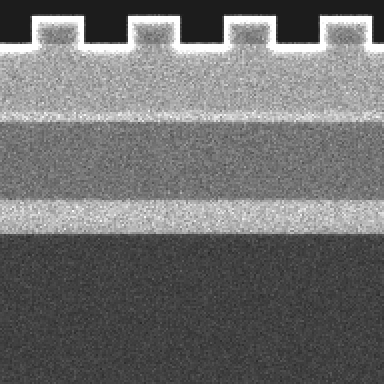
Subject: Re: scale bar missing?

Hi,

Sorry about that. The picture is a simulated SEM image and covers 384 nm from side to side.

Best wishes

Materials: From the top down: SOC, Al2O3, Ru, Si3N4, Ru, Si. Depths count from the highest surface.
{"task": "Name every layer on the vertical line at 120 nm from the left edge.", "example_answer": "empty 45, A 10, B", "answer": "empty 28, Al2O3 68, Ru 10, Si3N4 78, Ru 34, Si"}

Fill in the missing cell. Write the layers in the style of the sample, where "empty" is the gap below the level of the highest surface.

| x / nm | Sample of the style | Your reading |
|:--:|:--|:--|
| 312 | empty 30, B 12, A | empty 28, Al2O3 68, Ru 10, Si3N4 78, Ru 34, Si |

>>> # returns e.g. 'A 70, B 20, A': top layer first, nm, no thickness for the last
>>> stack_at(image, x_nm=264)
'SOC 28, Al2O3 68, Ru 10, Si3N4 78, Ru 34, Si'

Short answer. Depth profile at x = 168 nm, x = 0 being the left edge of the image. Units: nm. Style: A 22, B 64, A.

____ SOC 28, Al2O3 68, Ru 10, Si3N4 78, Ru 34, Si